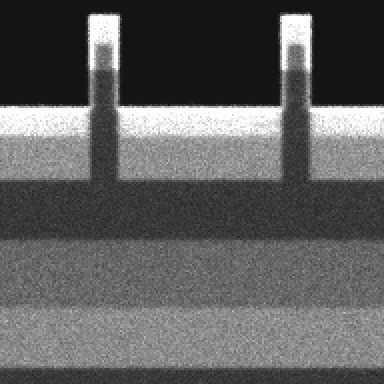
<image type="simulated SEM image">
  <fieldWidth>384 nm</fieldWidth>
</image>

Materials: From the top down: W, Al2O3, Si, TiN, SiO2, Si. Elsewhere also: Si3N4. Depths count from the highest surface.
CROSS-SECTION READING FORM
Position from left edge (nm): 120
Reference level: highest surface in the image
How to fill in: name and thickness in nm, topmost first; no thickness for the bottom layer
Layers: empty 92, W 28, Al2O3 44, Si 60, TiN 68, SiO2 60, Si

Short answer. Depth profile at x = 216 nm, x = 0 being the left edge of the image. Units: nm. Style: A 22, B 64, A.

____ empty 92, W 28, Al2O3 44, Si 60, TiN 68, SiO2 60, Si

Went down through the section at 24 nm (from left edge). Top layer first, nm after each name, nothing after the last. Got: empty 92, W 28, Al2O3 44, Si 60, TiN 68, SiO2 60, Si